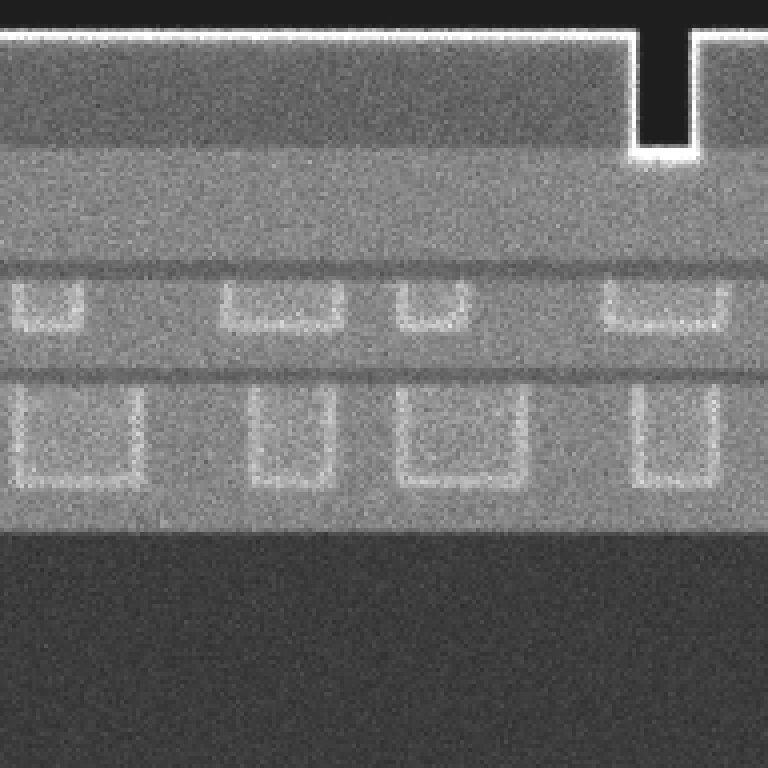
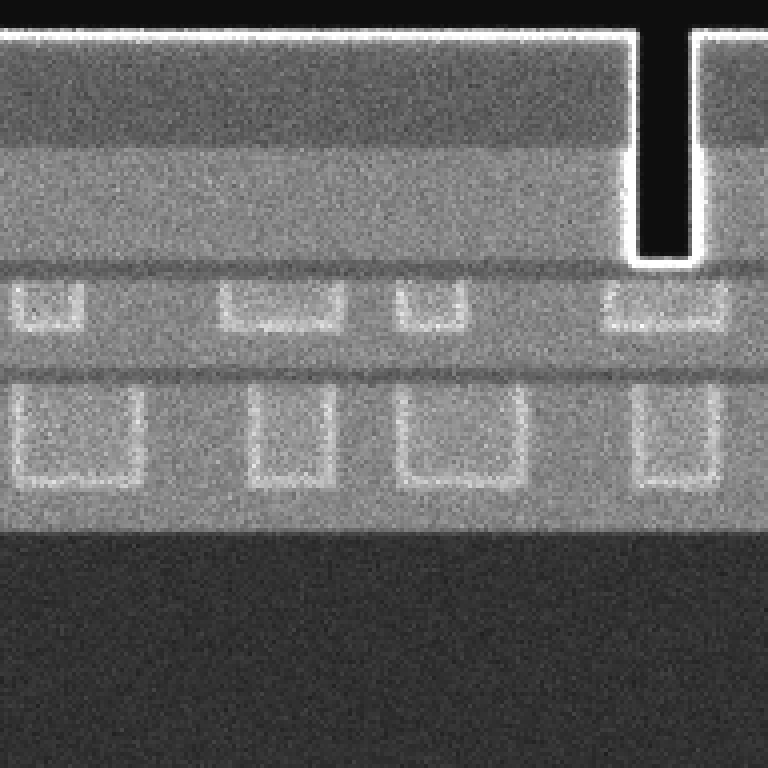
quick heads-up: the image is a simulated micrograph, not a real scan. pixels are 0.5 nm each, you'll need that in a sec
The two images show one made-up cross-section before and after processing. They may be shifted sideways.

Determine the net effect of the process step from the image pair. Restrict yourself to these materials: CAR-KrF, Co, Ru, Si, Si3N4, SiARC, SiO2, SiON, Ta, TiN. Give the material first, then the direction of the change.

SiO2: removed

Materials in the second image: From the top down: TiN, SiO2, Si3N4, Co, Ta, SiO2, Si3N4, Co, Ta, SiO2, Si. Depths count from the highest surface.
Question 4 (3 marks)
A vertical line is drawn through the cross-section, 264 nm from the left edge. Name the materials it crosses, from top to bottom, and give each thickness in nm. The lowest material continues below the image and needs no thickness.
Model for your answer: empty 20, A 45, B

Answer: TiN 58, SiO2 56, Si3N4 10, SiO2 44, Si3N4 8, SiO2 74, Si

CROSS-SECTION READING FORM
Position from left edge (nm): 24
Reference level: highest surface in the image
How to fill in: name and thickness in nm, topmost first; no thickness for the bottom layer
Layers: TiN 58, SiO2 56, Si3N4 10, Co 20, Ta 6, SiO2 18, Si3N4 8, Co 46, Ta 6, SiO2 22, Si